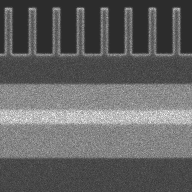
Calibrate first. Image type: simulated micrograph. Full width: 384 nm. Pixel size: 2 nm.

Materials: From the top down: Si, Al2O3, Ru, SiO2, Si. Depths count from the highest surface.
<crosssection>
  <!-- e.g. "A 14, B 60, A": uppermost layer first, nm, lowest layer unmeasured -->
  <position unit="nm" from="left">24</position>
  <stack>empty 92, Si 60, Al2O3 52, Ru 28, SiO2 68, Si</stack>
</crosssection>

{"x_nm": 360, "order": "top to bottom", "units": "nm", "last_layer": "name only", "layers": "empty 92, Si 60, Al2O3 52, Ru 28, SiO2 68, Si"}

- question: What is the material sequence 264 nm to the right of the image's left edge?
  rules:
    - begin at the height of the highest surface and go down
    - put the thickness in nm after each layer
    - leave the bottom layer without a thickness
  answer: empty 92, Si 60, Al2O3 52, Ru 28, SiO2 68, Si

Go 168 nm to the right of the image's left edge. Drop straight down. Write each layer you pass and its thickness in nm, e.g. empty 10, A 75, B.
empty 92, Si 60, Al2O3 52, Ru 28, SiO2 68, Si